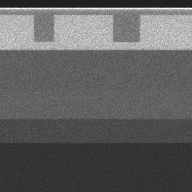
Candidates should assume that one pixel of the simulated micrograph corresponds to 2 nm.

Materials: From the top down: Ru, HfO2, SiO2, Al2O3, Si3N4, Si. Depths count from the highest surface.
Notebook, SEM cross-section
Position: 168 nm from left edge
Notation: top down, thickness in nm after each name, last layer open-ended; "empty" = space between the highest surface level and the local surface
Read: Ru 14, HfO2 70, SiO2 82, Al2O3 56, Si3N4 48, Si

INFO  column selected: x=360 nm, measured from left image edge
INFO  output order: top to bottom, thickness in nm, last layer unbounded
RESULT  Ru 14, HfO2 70, SiO2 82, Al2O3 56, Si3N4 48, Si